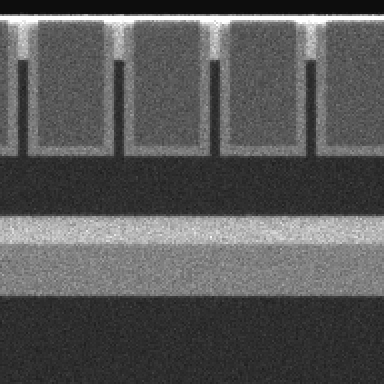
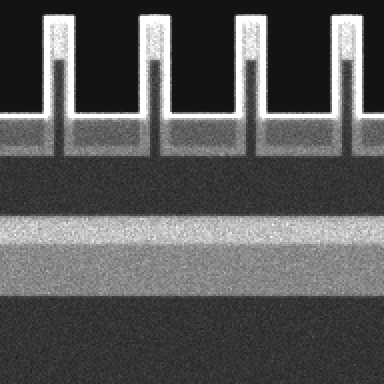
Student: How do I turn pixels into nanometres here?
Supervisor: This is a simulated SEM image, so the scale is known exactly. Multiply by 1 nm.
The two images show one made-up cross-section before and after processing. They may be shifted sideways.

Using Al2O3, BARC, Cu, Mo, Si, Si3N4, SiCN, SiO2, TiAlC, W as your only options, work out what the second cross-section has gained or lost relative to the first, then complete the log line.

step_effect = removed Si3N4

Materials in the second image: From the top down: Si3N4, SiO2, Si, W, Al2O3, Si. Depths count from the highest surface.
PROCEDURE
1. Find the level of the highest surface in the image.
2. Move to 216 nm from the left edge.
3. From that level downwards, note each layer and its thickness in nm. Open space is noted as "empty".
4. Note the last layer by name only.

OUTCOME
empty 98, Si3N4 32, SiO2 10, Si 60, W 28, Al2O3 52, Si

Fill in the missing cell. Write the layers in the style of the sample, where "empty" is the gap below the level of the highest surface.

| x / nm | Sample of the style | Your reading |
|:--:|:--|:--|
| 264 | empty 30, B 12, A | SiO2 140, Si 60, W 28, Al2O3 52, Si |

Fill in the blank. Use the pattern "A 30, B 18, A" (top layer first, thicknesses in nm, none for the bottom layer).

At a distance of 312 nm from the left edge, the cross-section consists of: empty 98, Si3N4 32, SiO2 10, Si 60, W 28, Al2O3 52, Si